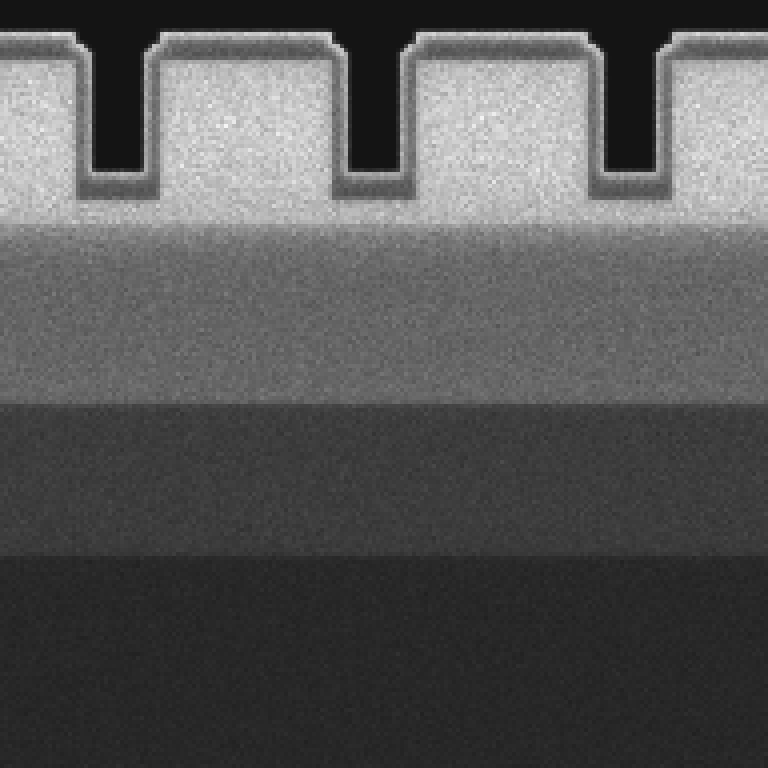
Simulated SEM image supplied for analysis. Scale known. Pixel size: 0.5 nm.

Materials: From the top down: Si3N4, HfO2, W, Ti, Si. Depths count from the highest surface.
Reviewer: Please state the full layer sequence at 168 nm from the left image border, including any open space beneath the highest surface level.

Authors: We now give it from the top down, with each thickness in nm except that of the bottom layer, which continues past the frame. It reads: empty 6, Si3N4 78, HfO2 12, W 90, Ti 76, Si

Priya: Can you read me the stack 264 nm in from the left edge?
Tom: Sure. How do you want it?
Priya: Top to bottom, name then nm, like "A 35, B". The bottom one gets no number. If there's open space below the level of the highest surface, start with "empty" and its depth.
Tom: Si3N4 14, HfO2 82, W 90, Ti 76, Si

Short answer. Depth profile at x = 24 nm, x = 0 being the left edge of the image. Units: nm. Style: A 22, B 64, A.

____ Si3N4 14, HfO2 82, W 90, Ti 76, Si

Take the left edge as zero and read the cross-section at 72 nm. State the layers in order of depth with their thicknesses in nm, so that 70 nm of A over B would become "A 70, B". empty 10, Si3N4 74, HfO2 12, W 90, Ti 76, Si